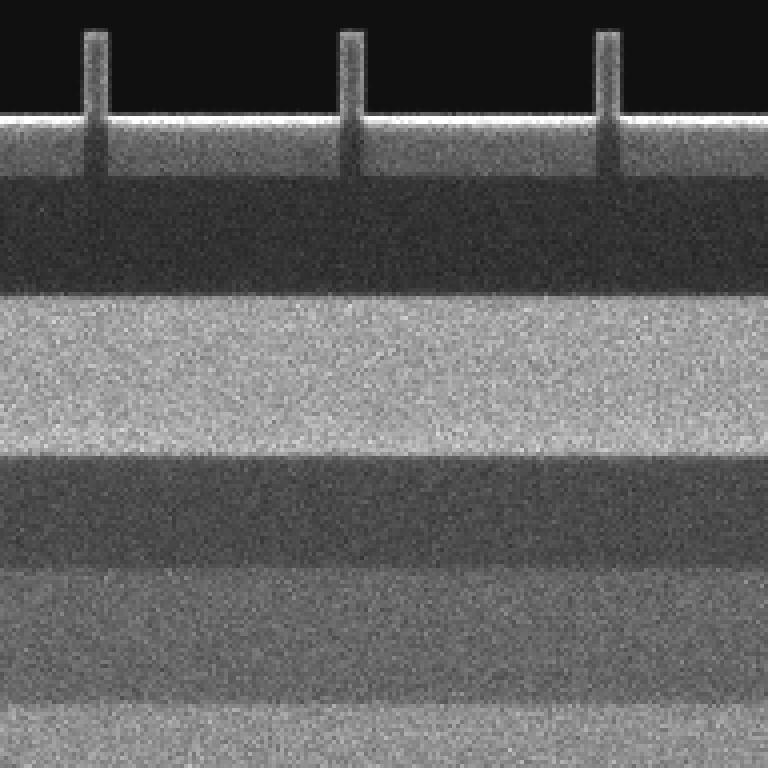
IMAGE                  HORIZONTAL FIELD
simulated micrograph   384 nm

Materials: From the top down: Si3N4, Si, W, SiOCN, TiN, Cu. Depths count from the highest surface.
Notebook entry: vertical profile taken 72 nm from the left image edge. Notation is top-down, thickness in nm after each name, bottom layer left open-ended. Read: empty 42, Si3N4 30, Si 60, W 80, SiOCN 56, TiN 68, Cu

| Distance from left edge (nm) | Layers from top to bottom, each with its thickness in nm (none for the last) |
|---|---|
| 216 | empty 42, Si3N4 30, Si 60, W 80, SiOCN 56, TiN 68, Cu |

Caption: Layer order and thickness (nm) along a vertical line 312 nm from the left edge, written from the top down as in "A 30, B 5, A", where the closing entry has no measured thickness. empty 42, Si3N4 30, Si 60, W 80, SiOCN 56, TiN 68, Cu